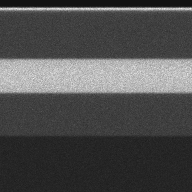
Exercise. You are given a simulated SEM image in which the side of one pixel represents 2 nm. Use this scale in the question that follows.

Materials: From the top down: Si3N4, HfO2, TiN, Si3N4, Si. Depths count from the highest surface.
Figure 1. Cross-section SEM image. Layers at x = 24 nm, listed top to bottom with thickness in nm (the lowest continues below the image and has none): Si3N4 102, HfO2 68, TiN 10, Si3N4 76, Si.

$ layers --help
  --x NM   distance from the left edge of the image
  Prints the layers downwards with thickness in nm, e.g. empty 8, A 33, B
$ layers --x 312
Si3N4 102, HfO2 68, TiN 10, Si3N4 76, Si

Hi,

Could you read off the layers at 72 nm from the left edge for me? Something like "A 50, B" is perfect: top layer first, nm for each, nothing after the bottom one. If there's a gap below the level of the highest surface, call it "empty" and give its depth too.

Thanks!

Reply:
Si3N4 102, HfO2 68, TiN 10, Si3N4 76, Si